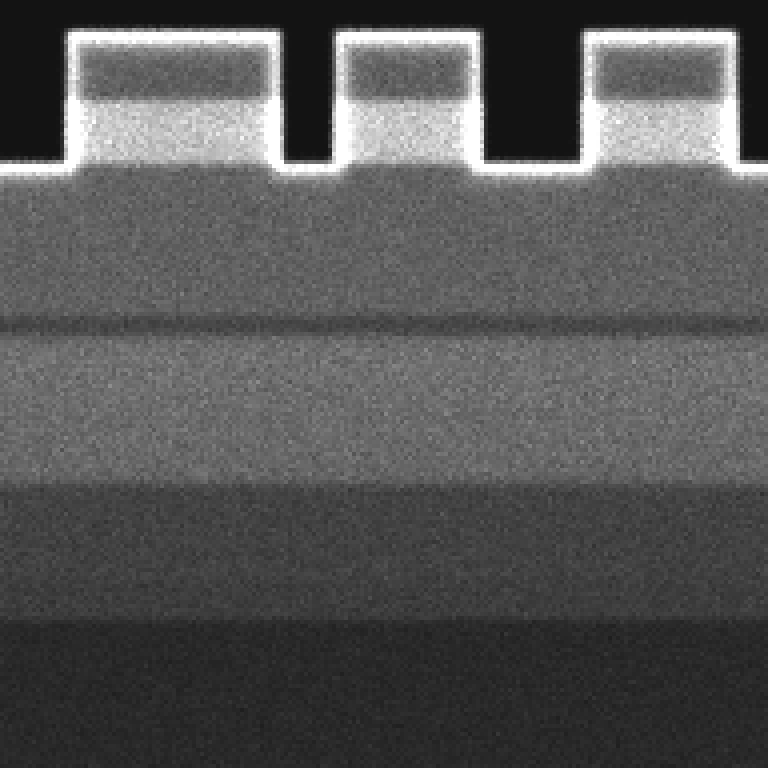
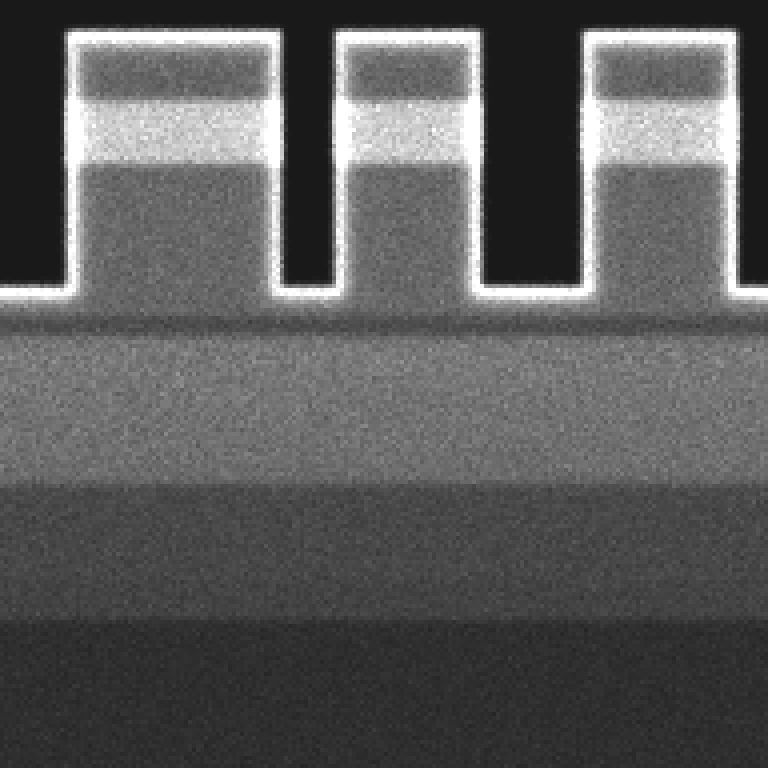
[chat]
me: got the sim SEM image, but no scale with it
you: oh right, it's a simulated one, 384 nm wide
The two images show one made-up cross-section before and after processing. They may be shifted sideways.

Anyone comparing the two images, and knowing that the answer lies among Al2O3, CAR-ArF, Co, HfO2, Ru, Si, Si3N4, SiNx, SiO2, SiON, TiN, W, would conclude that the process removed Al2O3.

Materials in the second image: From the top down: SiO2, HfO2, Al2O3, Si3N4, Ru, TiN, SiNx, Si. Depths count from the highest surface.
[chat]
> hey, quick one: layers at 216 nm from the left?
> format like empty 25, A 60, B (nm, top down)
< SiO2 34, HfO2 32, Al2O3 76, Si3N4 10, Ru 74, TiN 48, SiNx 20, Si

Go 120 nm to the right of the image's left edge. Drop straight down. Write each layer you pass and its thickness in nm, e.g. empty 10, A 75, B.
SiO2 34, HfO2 32, Al2O3 76, Si3N4 10, Ru 74, TiN 48, SiNx 20, Si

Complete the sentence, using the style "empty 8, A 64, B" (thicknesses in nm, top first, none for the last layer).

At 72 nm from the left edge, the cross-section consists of SiO2 34, HfO2 32, Al2O3 76, Si3N4 10, Ru 74, TiN 48, SiNx 20, Si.